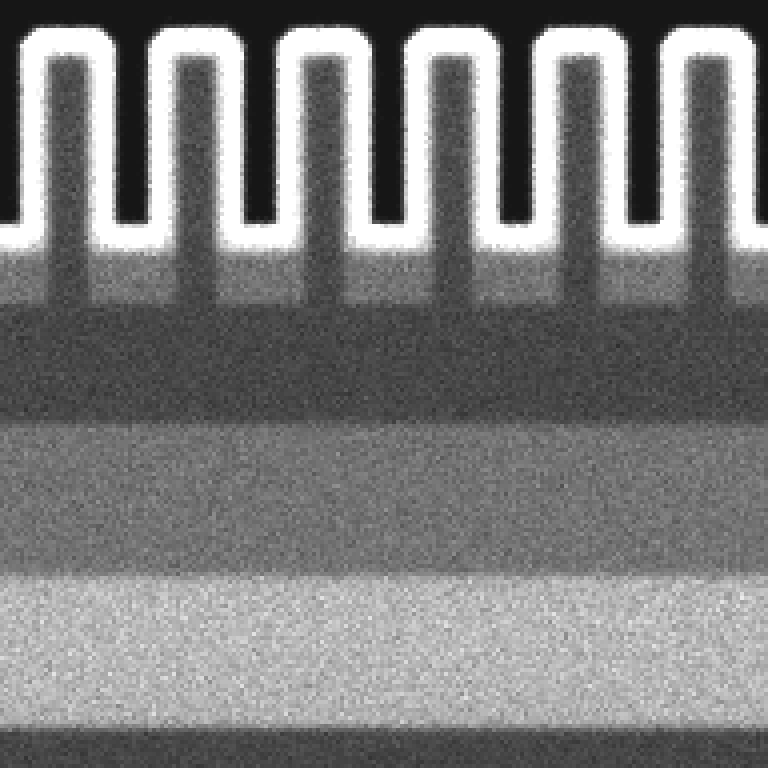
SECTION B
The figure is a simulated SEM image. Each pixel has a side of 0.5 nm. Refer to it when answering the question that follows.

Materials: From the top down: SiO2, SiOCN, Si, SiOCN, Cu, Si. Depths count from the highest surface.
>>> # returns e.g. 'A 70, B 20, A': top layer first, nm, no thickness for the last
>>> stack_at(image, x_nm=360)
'SiO2 12, Si 184, SiOCN 76, Cu 76, Si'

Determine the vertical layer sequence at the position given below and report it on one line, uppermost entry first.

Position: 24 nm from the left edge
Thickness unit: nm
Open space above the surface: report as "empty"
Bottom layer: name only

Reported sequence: SiO2 12, Si 184, SiOCN 76, Cu 76, Si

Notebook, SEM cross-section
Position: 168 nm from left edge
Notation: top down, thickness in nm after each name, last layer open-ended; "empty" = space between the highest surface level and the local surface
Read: SiO2 12, Si 184, SiOCN 76, Cu 76, Si